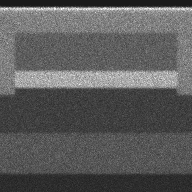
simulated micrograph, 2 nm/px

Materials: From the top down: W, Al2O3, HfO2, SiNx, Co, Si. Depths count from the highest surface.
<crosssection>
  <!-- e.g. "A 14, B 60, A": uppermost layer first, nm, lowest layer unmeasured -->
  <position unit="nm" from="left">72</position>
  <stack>W 50, Al2O3 76, HfO2 34, SiNx 90, Co 82, Si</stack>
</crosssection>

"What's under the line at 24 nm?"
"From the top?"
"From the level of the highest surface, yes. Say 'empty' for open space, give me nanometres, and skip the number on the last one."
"W 174, SiNx 76, Co 82, Si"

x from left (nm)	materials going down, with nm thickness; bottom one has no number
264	W 50, Al2O3 76, HfO2 34, SiNx 90, Co 82, Si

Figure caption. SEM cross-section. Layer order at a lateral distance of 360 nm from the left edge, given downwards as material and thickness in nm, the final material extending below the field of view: W 174, SiNx 76, Co 82, Si